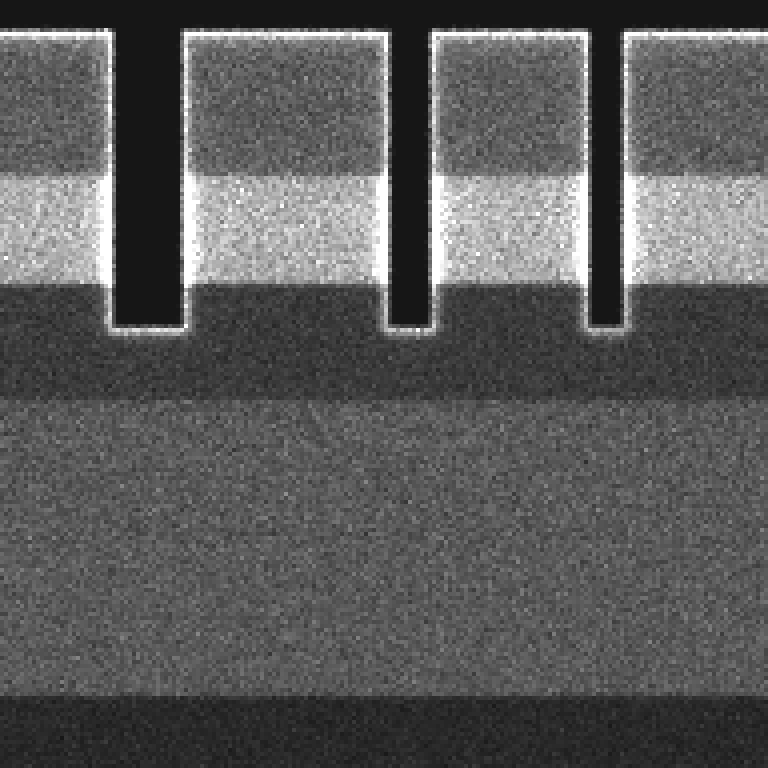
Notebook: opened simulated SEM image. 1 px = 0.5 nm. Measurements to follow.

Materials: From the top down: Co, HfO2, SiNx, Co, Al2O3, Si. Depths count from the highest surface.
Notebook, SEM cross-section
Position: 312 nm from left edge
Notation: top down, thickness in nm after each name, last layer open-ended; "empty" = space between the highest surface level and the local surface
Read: Co 72, HfO2 54, SiNx 58, Co 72, Al2O3 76, Si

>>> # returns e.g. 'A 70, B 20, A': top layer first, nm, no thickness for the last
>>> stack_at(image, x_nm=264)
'Co 72, HfO2 54, SiNx 58, Co 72, Al2O3 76, Si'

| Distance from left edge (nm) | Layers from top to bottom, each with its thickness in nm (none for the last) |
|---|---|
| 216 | Co 72, HfO2 54, SiNx 58, Co 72, Al2O3 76, Si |